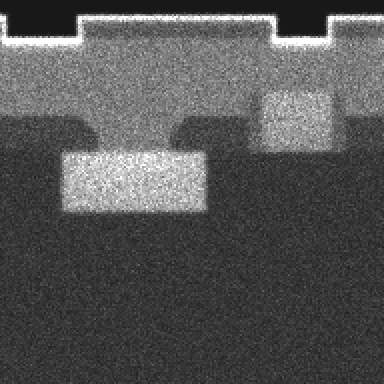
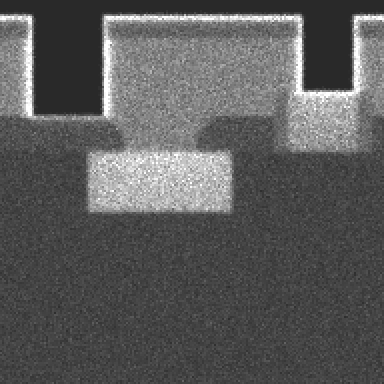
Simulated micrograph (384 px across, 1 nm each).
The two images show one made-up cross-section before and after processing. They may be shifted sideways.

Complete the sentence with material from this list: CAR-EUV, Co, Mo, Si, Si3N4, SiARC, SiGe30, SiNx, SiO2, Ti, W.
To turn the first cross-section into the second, SiO2 must be removed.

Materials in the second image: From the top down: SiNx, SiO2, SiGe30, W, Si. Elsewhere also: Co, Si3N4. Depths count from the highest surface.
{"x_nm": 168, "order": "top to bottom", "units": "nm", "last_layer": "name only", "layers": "SiNx 22, SiO2 114, W 60, Si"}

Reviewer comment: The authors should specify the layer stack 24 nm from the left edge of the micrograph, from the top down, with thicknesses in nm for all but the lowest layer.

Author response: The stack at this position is SiNx 22, SiO2 78, SiGe30 36, Si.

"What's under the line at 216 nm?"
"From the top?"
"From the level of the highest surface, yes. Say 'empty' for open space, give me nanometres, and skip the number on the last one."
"SiNx 22, SiO2 78, SiGe30 36, W 60, Si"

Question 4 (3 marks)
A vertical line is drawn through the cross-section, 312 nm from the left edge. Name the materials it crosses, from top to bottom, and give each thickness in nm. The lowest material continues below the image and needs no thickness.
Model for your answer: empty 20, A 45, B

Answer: empty 76, Co 60, Si